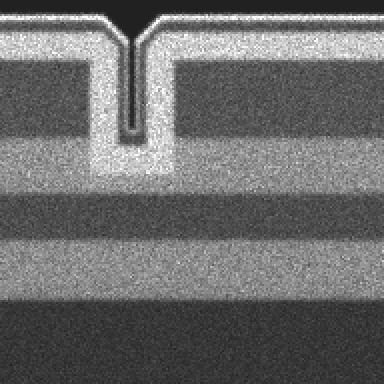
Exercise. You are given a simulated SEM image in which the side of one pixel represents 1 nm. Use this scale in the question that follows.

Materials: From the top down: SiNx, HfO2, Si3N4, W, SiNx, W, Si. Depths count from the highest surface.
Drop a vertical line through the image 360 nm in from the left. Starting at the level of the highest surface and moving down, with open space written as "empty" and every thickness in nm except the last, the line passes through SiNx 16, HfO2 28, Si3N4 78, W 56, SiNx 46, W 60, Si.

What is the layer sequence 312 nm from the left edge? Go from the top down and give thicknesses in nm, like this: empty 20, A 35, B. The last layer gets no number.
SiNx 16, HfO2 28, Si3N4 78, W 56, SiNx 46, W 60, Si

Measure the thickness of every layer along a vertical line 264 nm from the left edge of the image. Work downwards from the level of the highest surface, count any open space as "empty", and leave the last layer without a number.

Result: SiNx 16, HfO2 28, Si3N4 78, W 56, SiNx 46, W 60, Si